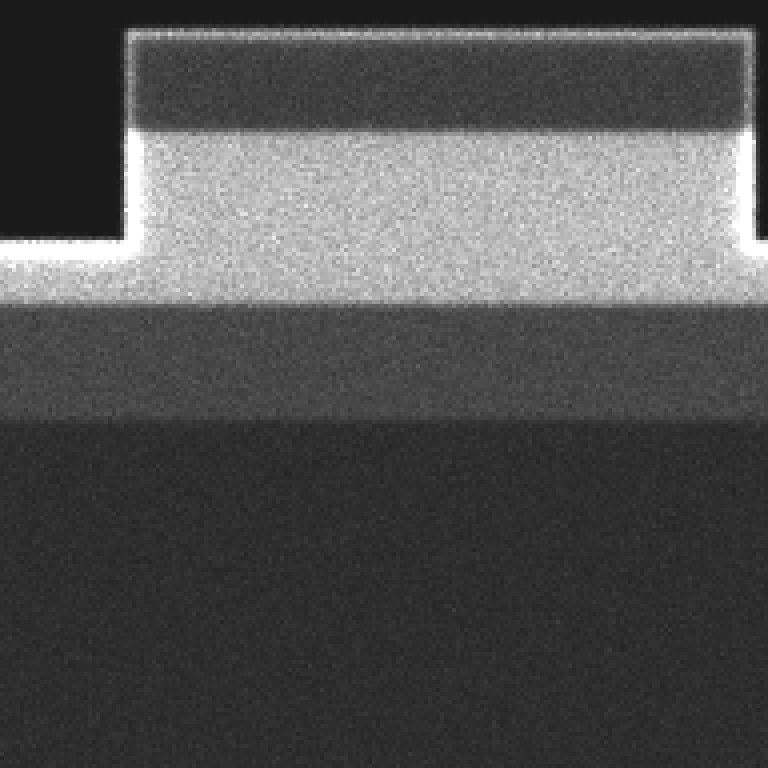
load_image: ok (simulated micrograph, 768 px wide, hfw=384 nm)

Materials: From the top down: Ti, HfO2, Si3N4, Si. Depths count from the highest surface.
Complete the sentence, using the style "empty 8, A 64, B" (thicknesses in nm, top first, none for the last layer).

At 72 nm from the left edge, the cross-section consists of Ti 50, HfO2 86, Si3N4 58, Si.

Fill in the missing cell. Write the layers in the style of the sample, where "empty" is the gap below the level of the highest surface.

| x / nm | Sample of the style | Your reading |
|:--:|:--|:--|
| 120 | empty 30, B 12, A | Ti 50, HfO2 86, Si3N4 58, Si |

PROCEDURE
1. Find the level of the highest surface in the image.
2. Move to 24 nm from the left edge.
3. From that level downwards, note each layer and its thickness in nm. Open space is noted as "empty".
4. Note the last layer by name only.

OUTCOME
empty 106, HfO2 30, Si3N4 58, Si